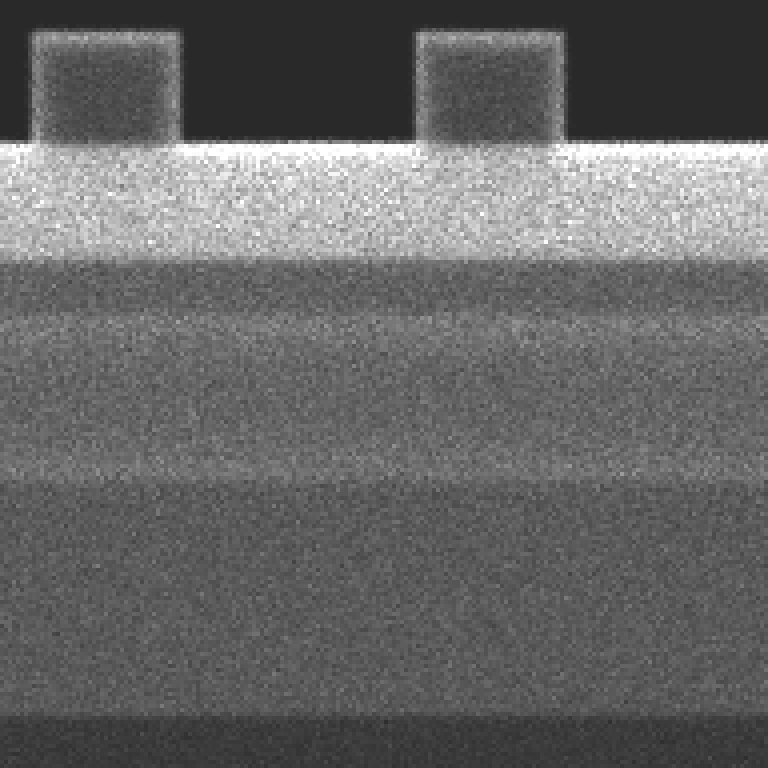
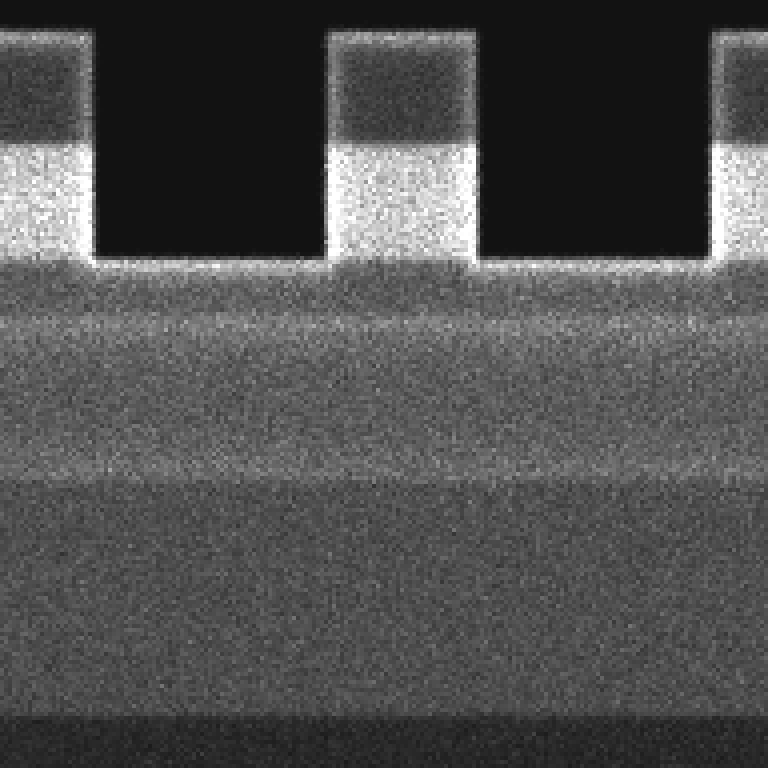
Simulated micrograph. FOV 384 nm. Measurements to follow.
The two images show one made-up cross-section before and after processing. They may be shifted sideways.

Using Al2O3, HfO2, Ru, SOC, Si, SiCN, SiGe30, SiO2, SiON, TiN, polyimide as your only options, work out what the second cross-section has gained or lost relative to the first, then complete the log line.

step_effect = removed HfO2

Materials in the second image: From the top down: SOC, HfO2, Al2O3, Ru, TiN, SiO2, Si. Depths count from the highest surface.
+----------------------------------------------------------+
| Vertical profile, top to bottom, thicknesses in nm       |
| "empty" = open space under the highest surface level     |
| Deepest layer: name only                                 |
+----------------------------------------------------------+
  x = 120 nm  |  empty 114, Al2O3 28, Ru 82, TiN 10, SiO2 108, Si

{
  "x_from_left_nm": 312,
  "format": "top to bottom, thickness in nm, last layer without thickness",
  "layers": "empty 114, Al2O3 28, Ru 82, TiN 10, SiO2 108, Si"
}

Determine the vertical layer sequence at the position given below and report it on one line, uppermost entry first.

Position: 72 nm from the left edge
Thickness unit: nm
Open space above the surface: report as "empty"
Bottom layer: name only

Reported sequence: empty 114, Al2O3 28, Ru 82, TiN 10, SiO2 108, Si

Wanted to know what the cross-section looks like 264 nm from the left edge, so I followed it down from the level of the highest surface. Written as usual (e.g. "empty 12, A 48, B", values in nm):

empty 114, Al2O3 28, Ru 82, TiN 10, SiO2 108, Si